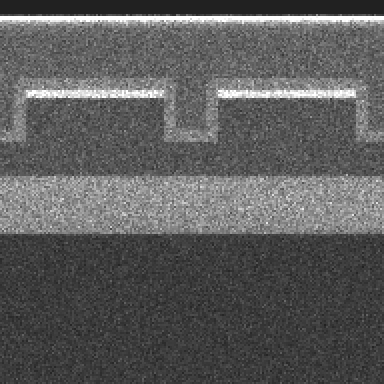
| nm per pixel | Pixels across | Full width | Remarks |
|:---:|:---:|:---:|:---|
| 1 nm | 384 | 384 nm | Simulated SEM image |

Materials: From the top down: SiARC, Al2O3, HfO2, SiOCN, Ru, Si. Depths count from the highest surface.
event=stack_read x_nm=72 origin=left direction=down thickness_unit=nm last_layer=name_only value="SiARC 62, Al2O3 12, HfO2 8, SiOCN 78, Ru 58, Si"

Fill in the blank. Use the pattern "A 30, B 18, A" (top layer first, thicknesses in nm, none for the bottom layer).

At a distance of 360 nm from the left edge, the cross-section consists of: SiARC 62, Al2O3 64, SiOCN 34, Ru 58, Si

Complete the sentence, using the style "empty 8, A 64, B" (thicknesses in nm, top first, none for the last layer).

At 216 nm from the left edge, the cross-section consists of SiARC 62, Al2O3 64, SiOCN 34, Ru 58, Si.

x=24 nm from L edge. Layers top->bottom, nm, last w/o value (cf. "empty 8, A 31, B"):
SiARC 62, Al2O3 64, SiOCN 34, Ru 58, Si